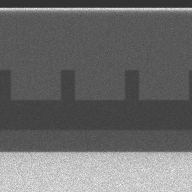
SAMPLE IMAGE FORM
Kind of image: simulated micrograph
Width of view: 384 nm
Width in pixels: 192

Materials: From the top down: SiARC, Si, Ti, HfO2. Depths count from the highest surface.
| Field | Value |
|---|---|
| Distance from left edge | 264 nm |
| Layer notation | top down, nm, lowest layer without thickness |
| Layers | SiARC 124, Si 120, Ti 44, HfO2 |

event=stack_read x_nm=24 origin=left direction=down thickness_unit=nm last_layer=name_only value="SiARC 184, Si 60, Ti 44, HfO2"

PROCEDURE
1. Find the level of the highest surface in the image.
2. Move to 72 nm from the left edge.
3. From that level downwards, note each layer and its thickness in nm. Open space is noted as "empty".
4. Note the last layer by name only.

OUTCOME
SiARC 184, Si 60, Ti 44, HfO2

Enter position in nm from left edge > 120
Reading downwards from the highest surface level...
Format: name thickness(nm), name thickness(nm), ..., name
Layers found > SiARC 184, Si 60, Ti 44, HfO2